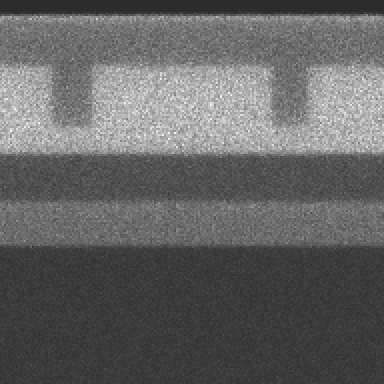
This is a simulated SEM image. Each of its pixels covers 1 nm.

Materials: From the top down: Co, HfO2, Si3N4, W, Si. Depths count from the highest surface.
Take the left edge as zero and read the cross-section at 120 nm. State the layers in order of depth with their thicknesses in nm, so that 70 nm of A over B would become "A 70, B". Co 50, HfO2 88, Si3N4 48, W 44, Si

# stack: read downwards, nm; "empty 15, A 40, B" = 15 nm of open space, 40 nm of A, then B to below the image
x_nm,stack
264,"Co 50, HfO2 88, Si3N4 48, W 44, Si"